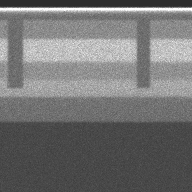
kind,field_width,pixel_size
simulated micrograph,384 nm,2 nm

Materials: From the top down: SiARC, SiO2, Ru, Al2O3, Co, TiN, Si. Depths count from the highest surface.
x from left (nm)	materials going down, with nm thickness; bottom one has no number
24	SiARC 160, Co 18, TiN 50, Si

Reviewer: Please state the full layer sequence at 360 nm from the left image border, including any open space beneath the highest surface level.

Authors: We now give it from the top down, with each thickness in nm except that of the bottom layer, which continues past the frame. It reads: SiARC 24, SiO2 38, Ru 46, Al2O3 36, Co 34, TiN 50, Si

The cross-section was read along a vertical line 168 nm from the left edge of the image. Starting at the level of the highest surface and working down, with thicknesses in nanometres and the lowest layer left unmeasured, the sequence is SiARC 24, SiO2 38, Ru 46, Al2O3 36, Co 34, TiN 50, Si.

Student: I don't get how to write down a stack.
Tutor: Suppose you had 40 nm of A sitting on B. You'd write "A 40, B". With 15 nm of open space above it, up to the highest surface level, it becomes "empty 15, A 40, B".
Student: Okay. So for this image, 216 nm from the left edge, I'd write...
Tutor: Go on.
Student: SiARC 24, SiO2 38, Ru 46, Al2O3 36, Co 34, TiN 50, Si